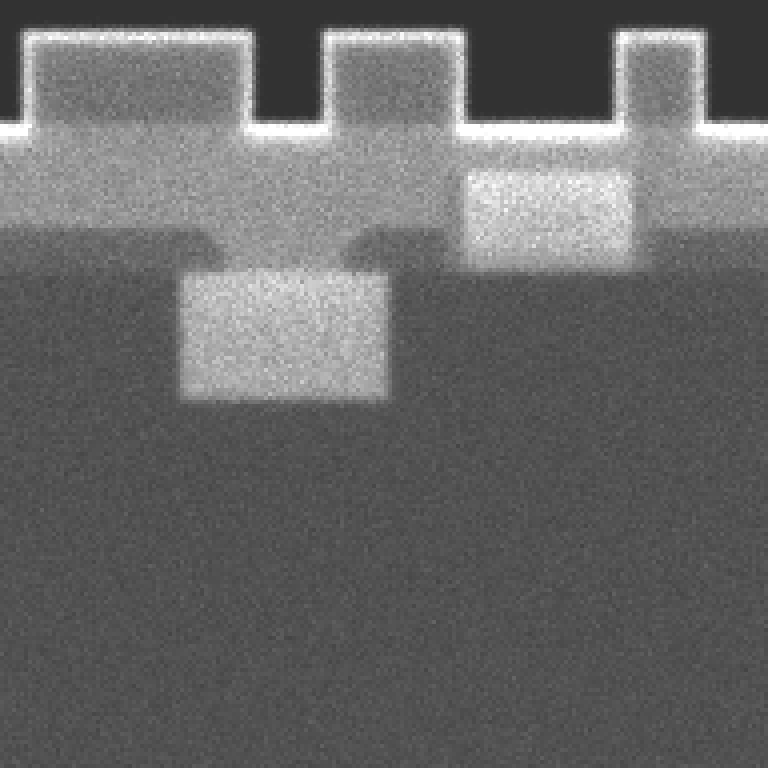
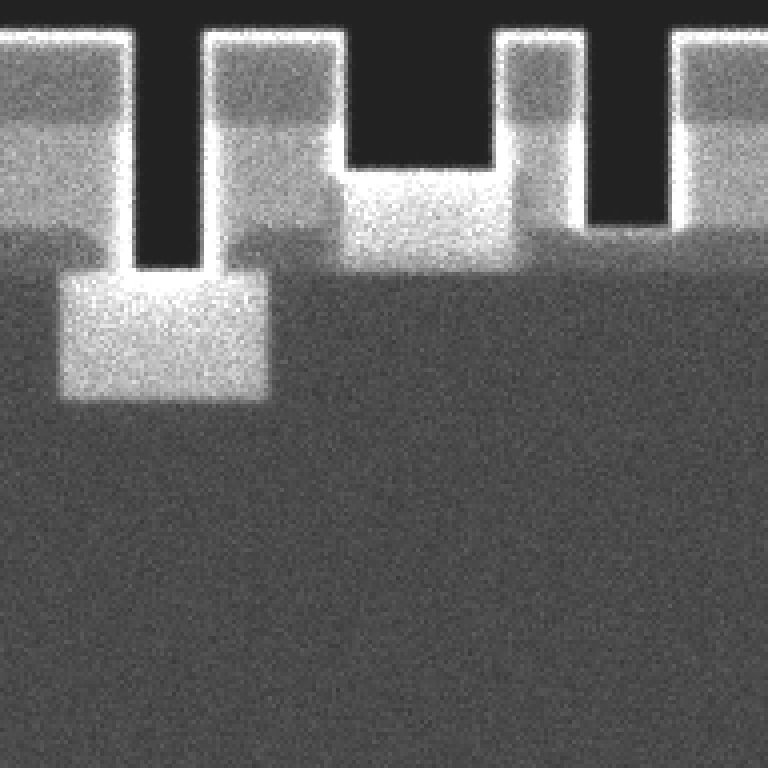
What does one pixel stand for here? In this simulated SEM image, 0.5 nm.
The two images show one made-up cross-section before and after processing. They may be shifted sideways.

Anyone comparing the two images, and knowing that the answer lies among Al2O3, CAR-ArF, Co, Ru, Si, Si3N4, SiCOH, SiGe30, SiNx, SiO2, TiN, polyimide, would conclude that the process removed SiO2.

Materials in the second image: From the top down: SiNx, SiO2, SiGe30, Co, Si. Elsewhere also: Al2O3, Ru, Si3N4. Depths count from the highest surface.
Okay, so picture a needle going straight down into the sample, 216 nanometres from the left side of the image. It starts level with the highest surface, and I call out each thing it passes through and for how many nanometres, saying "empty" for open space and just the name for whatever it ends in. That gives empty 70, Ru 40, Al2O3 10, Si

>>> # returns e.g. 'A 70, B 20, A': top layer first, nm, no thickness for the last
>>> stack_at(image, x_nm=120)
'SiNx 46, SiO2 54, SiGe30 20, Co 64, Si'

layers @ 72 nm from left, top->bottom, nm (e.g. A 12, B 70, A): empty 120, Co 64, Si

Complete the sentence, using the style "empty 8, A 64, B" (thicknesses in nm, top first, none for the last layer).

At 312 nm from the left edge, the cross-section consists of empty 98, SiGe30 22, Si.